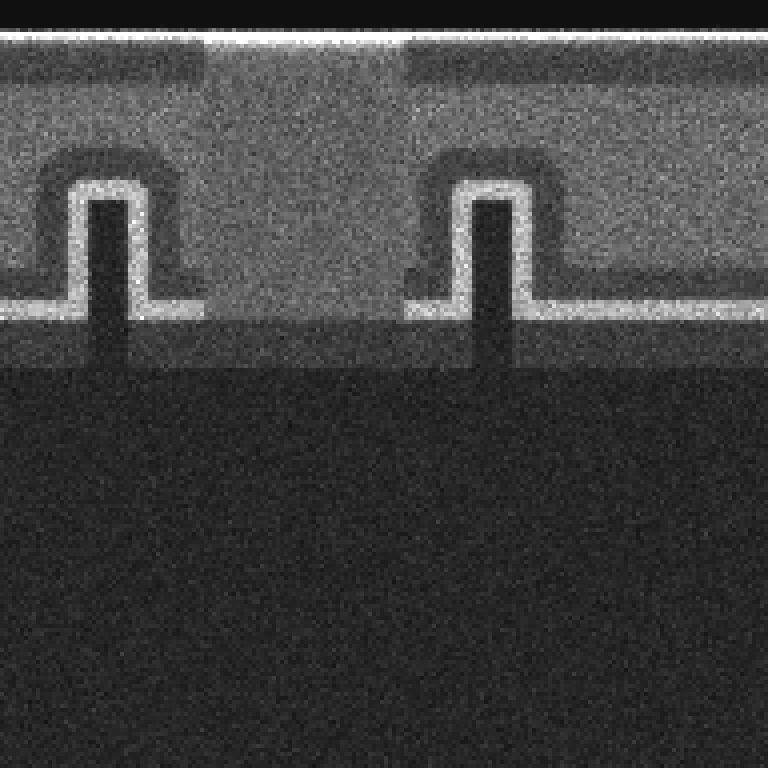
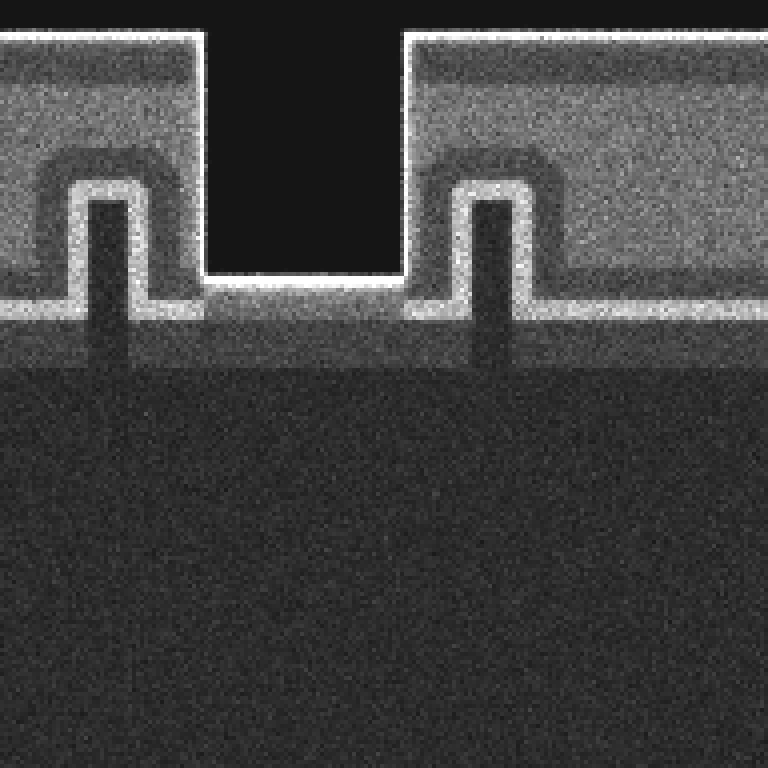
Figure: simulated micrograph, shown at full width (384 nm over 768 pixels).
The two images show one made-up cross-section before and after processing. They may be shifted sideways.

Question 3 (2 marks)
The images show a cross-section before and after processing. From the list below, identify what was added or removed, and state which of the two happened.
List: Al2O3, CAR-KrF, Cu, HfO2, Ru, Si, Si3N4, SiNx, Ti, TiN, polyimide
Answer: Al2O3 was removed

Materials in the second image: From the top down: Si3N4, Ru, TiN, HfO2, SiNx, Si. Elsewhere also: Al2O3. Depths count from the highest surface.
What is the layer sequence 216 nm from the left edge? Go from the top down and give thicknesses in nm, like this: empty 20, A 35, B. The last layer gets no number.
Si3N4 26, Ru 38, TiN 70, HfO2 10, SiNx 24, Si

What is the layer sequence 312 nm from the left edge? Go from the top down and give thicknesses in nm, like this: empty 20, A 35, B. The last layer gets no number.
Si3N4 26, Ru 92, TiN 16, HfO2 10, SiNx 24, Si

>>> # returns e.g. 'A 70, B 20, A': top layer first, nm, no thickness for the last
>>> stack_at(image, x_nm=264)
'Si3N4 26, Ru 32, TiN 20, HfO2 66, SiNx 24, Si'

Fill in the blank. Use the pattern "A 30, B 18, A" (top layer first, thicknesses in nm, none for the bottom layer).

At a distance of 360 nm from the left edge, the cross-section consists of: Si3N4 26, Ru 92, TiN 16, HfO2 10, SiNx 24, Si